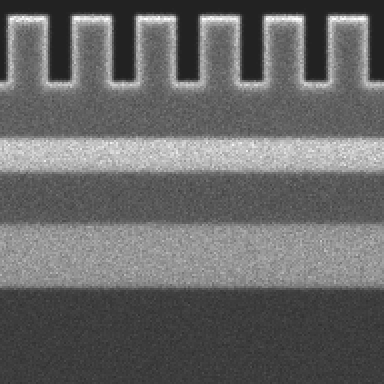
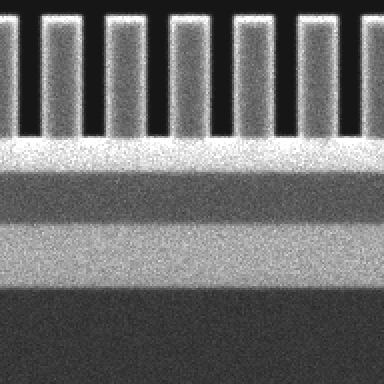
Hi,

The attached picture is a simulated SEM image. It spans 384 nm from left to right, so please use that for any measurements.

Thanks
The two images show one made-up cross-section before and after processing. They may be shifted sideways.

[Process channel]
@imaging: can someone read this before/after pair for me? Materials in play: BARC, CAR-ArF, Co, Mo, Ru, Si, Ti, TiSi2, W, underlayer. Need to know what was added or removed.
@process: underlayer removed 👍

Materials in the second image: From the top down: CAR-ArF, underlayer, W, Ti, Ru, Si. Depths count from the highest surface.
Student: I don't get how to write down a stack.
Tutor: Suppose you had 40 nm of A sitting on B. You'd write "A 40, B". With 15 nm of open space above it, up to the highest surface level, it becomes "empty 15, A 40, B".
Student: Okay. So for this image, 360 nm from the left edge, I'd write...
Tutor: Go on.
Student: empty 122, W 34, Ti 52, Ru 64, Si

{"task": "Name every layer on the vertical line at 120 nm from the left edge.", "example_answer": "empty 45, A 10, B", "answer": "CAR-ArF 66, underlayer 56, W 34, Ti 52, Ru 64, Si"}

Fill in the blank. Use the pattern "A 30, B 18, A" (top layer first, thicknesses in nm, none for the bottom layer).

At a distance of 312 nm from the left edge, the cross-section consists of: CAR-ArF 66, underlayer 56, W 34, Ti 52, Ru 64, Si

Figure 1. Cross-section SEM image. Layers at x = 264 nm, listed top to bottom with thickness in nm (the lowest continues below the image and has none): CAR-ArF 66, underlayer 56, W 34, Ti 52, Ru 64, Si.